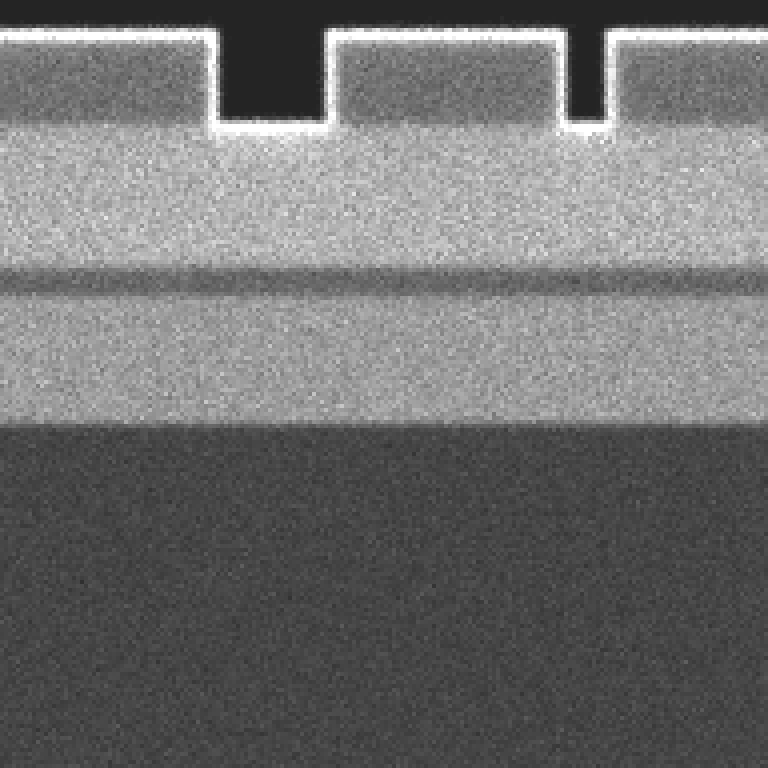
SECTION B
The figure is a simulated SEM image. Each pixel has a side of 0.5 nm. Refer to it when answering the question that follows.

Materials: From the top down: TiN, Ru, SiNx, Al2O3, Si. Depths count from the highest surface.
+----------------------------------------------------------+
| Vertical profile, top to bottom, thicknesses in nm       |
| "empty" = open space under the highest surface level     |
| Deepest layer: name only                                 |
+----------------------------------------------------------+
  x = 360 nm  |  TiN 46, Ru 72, SiNx 14, Al2O3 64, Si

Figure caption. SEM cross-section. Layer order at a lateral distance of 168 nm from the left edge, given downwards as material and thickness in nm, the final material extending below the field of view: TiN 46, Ru 72, SiNx 14, Al2O3 64, Si